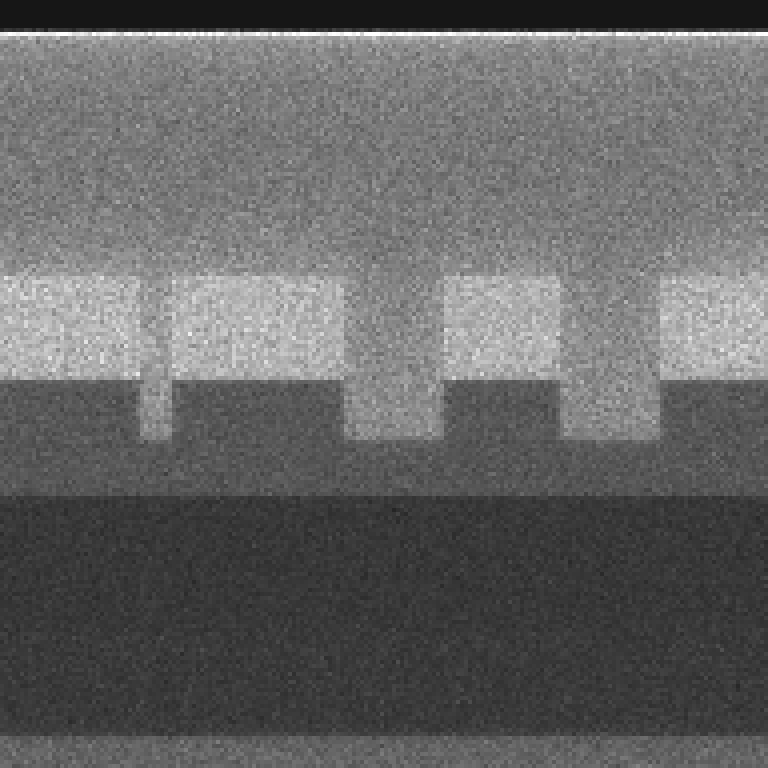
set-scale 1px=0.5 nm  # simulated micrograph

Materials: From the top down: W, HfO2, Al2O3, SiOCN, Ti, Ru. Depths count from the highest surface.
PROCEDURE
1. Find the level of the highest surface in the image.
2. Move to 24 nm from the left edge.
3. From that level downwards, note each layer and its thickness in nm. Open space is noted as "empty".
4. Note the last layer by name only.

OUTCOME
W 122, HfO2 52, Al2O3 58, SiOCN 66, Ti 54, Ru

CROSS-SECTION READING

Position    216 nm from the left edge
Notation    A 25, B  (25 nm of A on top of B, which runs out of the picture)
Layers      W 204, Al2O3 28, SiOCN 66, Ti 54, Ru